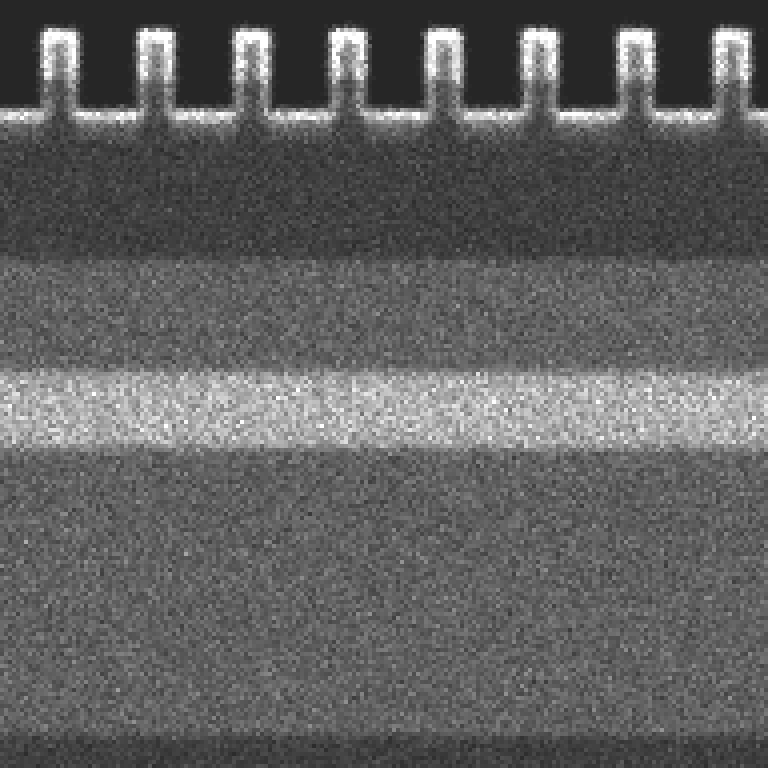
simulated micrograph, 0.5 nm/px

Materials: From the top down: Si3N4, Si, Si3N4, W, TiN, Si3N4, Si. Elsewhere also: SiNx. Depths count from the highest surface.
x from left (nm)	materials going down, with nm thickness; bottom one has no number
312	Si3N4 24, Si 90, Si3N4 56, W 38, TiN 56, Si3N4 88, Si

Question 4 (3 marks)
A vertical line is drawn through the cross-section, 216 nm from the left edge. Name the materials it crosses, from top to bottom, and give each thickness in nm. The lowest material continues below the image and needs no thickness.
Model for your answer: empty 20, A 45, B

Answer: Si3N4 24, Si 90, Si3N4 56, W 38, TiN 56, Si3N4 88, Si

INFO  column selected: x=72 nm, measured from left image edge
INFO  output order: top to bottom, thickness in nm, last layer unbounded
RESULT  Si3N4 24, Si 90, Si3N4 56, W 38, TiN 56, Si3N4 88, Si